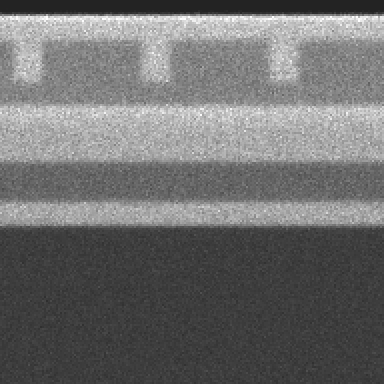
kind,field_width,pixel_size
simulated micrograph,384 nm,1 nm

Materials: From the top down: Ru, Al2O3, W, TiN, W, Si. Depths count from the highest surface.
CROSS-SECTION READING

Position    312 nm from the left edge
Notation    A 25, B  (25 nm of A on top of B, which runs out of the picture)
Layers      Ru 24, Al2O3 66, W 56, TiN 40, W 24, Si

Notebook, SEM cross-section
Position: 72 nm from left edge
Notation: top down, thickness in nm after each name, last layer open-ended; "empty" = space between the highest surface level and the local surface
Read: Ru 24, Al2O3 66, W 56, TiN 40, W 24, Si